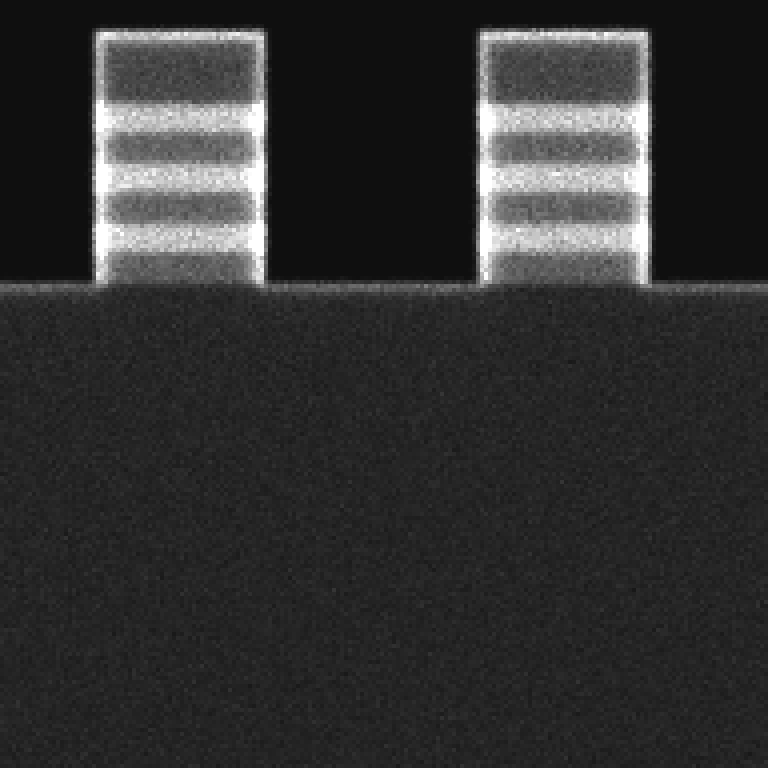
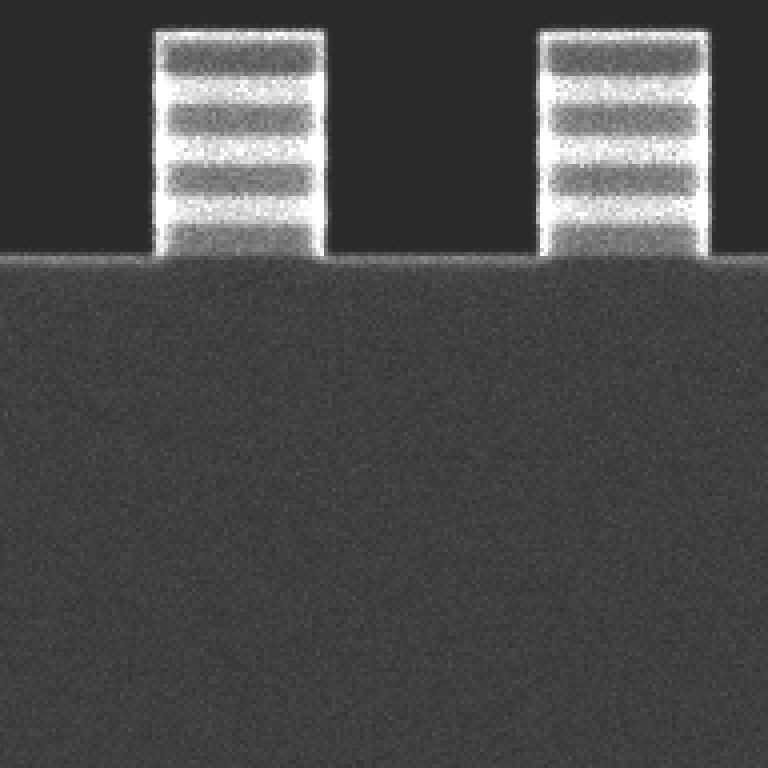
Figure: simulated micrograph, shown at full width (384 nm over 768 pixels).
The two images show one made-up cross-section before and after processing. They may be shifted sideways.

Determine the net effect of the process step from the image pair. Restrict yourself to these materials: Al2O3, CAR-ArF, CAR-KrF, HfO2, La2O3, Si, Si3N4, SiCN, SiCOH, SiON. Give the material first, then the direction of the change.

Si3N4: removed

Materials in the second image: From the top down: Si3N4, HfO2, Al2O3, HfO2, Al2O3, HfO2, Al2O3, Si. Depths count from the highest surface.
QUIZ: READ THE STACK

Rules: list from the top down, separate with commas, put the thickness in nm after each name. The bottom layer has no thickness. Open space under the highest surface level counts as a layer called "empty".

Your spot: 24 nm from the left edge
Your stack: empty 112, Si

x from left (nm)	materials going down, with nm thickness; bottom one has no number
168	empty 112, Si